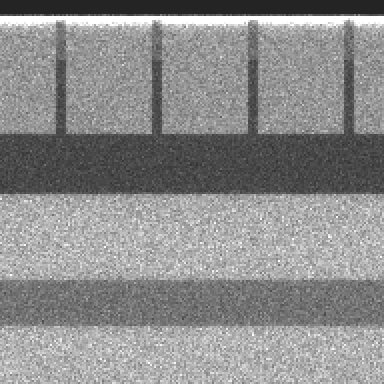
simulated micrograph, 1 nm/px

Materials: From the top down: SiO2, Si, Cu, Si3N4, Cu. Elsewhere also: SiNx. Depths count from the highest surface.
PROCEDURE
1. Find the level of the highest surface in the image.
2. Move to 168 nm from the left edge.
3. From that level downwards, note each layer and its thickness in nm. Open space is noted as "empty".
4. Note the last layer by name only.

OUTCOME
SiO2 118, Si 60, Cu 86, Si3N4 46, Cu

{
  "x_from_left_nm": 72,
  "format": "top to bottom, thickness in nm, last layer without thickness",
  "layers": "SiO2 118, Si 60, Cu 86, Si3N4 46, Cu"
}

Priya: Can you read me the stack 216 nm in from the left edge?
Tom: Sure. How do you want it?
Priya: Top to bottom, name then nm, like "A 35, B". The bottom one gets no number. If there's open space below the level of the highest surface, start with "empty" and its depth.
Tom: SiO2 118, Si 60, Cu 86, Si3N4 46, Cu